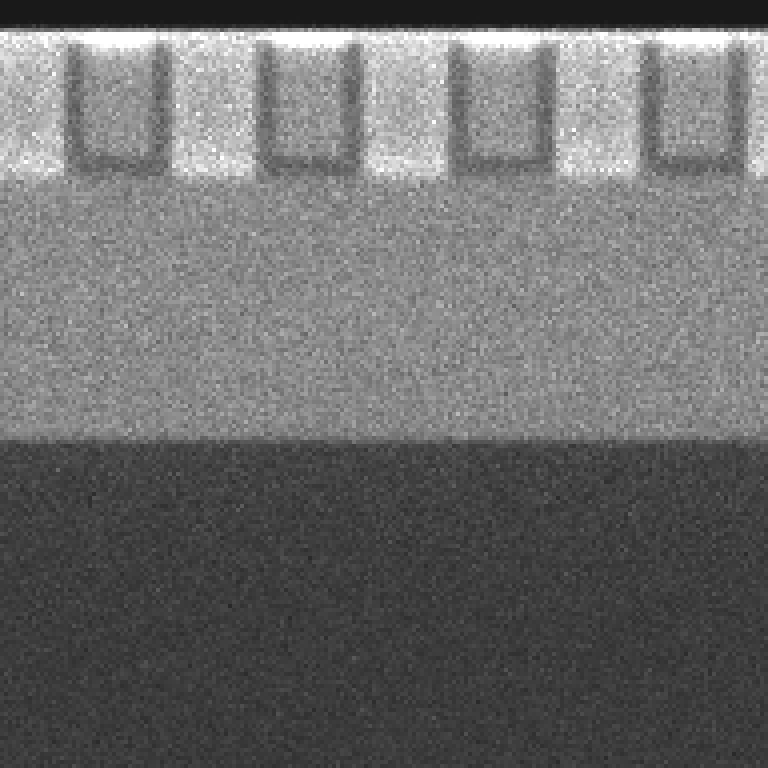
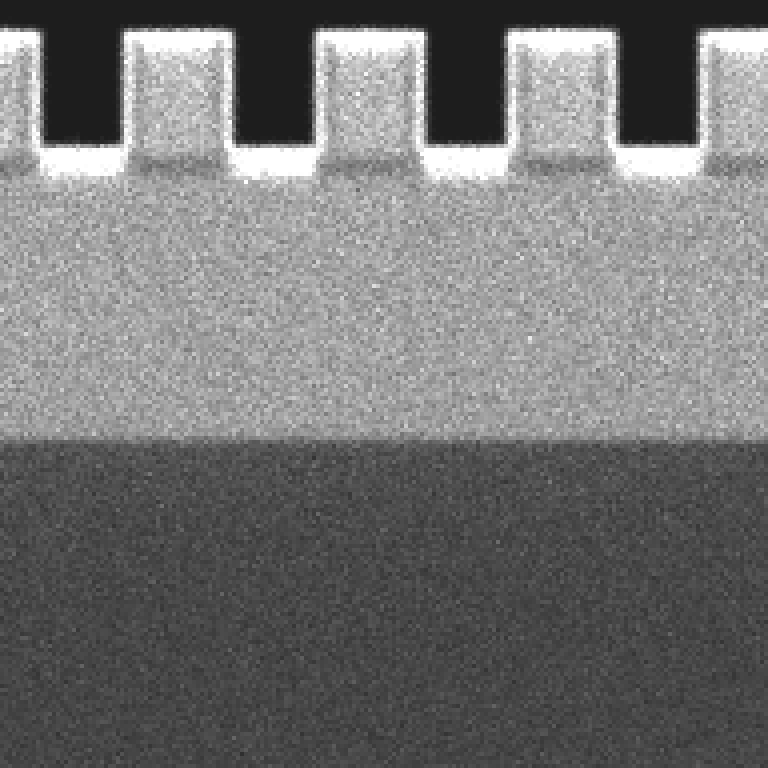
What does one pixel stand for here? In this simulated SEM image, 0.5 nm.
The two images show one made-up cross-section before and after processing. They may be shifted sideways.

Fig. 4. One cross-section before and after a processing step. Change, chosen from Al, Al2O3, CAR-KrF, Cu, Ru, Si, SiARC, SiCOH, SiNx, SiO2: Ru removed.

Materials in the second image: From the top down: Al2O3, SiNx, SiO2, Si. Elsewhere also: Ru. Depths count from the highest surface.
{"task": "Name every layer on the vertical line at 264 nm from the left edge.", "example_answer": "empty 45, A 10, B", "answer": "Al2O3 62, SiNx 10, SiO2 132, Si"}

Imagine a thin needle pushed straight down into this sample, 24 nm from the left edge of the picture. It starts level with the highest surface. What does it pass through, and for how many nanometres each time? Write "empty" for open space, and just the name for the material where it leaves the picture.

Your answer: empty 58, Ru 14, SiO2 132, Si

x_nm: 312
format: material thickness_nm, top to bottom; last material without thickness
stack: empty 58, Ru 14, SiO2 132, Si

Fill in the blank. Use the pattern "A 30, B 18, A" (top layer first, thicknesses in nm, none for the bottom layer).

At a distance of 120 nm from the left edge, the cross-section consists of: empty 58, Ru 14, SiO2 132, Si